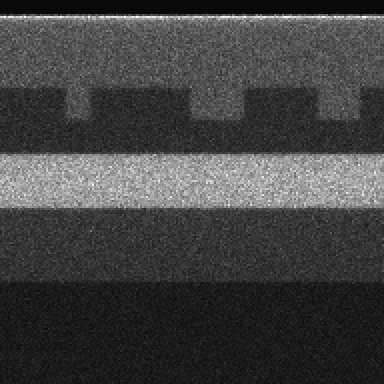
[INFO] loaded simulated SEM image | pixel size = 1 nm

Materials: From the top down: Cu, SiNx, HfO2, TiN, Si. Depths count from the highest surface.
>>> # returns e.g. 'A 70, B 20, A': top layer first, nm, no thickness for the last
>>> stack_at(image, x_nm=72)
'Cu 104, SiNx 34, HfO2 54, TiN 74, Si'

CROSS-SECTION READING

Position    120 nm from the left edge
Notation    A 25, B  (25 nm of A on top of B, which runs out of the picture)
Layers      Cu 72, SiNx 66, HfO2 54, TiN 74, Si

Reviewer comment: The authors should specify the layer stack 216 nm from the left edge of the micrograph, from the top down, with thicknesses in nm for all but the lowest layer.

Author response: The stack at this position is Cu 104, SiNx 34, HfO2 54, TiN 74, Si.